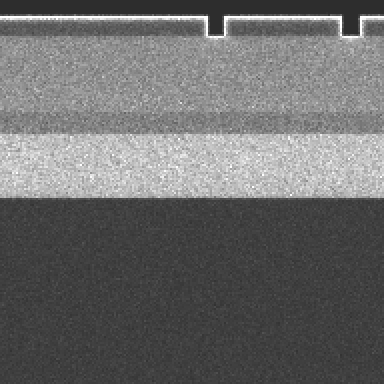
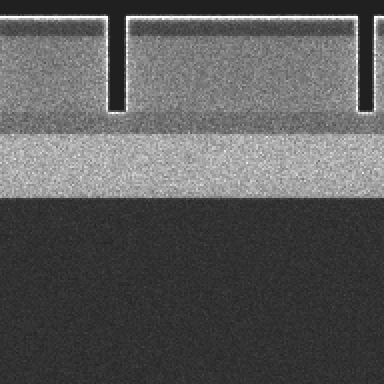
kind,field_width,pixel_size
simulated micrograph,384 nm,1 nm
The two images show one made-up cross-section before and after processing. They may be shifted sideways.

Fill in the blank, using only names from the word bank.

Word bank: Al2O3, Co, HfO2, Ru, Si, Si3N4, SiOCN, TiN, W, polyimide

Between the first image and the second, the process removed W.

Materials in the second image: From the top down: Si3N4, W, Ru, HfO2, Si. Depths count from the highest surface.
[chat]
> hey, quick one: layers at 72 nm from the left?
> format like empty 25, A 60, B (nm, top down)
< Si3N4 20, W 76, Ru 22, HfO2 64, Si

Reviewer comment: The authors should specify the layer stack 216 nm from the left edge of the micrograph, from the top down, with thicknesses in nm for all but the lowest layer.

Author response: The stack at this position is Si3N4 20, W 76, Ru 22, HfO2 64, Si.